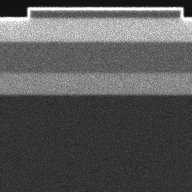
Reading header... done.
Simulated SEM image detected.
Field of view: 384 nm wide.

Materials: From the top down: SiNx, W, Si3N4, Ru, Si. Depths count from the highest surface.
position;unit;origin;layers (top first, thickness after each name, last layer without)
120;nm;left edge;SiNx 20, W 48, Si3N4 62, Ru 44, Si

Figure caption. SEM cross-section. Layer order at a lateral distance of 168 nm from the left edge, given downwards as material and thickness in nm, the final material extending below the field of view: SiNx 20, W 48, Si3N4 62, Ru 44, Si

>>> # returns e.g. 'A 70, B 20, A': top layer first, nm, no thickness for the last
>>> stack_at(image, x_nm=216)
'SiNx 20, W 48, Si3N4 62, Ru 44, Si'